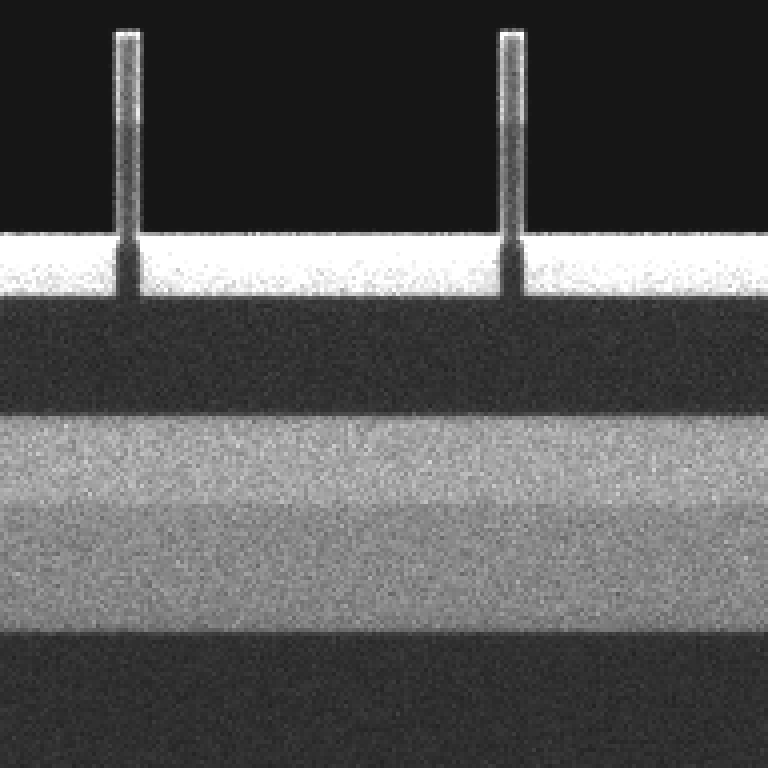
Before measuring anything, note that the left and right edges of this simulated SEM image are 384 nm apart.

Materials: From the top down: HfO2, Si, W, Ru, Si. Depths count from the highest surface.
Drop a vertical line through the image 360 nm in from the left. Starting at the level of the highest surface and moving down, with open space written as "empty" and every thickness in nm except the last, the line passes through empty 102, HfO2 30, Si 60, W 44, Ru 64, Si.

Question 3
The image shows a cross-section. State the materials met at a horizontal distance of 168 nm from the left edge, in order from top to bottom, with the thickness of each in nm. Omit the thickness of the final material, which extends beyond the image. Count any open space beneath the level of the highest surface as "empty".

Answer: empty 102, HfO2 30, Si 60, W 44, Ru 64, Si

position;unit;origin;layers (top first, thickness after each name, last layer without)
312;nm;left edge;empty 102, HfO2 30, Si 60, W 44, Ru 64, Si